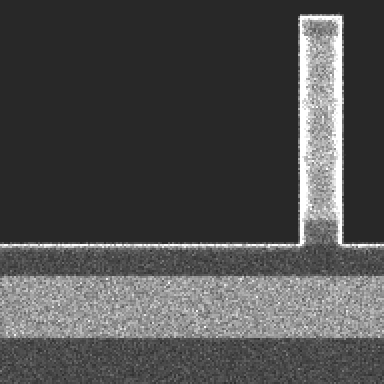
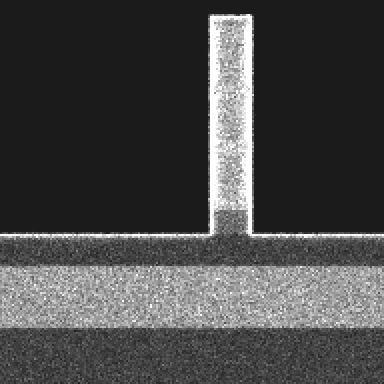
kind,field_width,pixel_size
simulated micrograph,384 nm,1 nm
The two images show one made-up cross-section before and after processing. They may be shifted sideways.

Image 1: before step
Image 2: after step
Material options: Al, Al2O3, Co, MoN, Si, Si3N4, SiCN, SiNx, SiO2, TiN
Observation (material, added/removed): TiN, removed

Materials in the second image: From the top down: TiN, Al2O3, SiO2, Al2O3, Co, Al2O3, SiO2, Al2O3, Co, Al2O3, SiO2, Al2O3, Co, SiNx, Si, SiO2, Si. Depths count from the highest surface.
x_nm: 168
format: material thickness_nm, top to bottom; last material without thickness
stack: empty 218, Si 32, SiO2 62, Si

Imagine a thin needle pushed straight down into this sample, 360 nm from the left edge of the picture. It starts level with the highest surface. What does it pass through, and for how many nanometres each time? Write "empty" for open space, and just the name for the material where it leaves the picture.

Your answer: empty 218, Si 32, SiO2 62, Si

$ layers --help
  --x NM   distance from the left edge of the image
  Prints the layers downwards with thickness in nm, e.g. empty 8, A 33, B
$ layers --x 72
empty 218, Si 32, SiO2 62, Si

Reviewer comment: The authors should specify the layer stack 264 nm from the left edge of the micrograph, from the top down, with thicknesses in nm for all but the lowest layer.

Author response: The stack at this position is empty 218, Si 32, SiO2 62, Si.